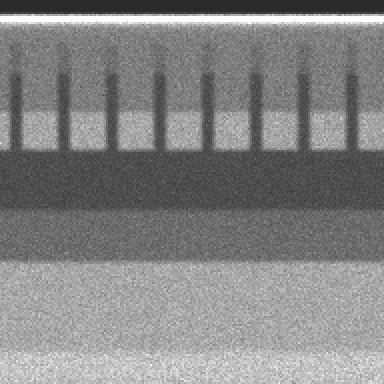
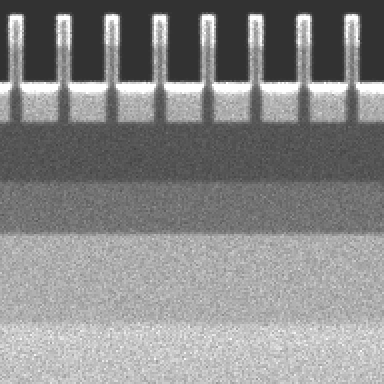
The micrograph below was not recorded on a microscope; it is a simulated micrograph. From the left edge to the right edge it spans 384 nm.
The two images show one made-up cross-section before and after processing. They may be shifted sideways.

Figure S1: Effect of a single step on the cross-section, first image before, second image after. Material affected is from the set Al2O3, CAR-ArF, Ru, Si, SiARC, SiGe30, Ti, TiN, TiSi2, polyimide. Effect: removed SiARC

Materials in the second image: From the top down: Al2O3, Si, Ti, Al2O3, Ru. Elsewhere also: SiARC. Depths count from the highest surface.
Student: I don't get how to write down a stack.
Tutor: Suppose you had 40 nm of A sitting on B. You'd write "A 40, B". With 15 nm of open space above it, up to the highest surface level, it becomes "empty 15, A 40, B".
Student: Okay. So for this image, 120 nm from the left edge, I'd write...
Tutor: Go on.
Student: empty 68, Al2O3 38, Si 60, Ti 52, Al2O3 90, Ru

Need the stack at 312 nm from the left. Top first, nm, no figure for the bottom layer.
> empty 68, Al2O3 38, Si 60, Ti 52, Al2O3 90, Ru